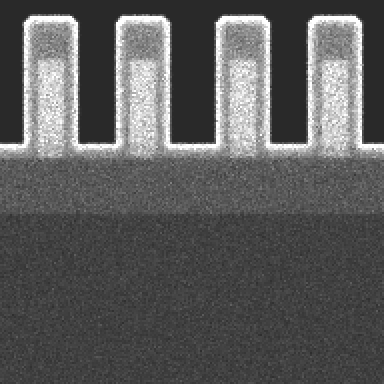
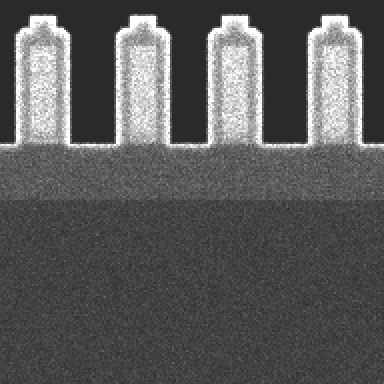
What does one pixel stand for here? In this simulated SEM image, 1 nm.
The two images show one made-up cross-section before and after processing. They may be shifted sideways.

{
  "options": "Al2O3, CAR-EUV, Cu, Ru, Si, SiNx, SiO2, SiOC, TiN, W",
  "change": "removed",
  "material": "SiO2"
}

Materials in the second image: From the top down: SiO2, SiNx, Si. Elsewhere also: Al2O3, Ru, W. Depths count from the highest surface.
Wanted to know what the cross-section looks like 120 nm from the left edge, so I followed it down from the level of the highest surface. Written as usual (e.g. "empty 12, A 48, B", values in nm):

empty 14, SiO2 114, SiNx 56, Si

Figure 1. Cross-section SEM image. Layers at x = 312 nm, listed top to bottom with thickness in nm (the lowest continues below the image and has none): empty 14, SiO2 114, SiNx 56, Si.